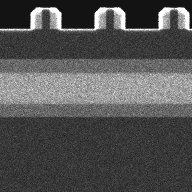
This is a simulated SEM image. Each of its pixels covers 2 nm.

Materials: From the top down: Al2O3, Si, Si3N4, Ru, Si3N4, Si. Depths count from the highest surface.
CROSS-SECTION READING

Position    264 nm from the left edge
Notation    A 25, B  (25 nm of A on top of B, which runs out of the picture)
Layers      empty 42, Si 60, Si3N4 28, Ru 62, Si3N4 26, Si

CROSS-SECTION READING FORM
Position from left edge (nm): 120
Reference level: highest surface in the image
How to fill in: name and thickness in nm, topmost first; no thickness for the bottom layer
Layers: empty 10, Al2O3 32, Si 60, Si3N4 28, Ru 62, Si3N4 26, Si